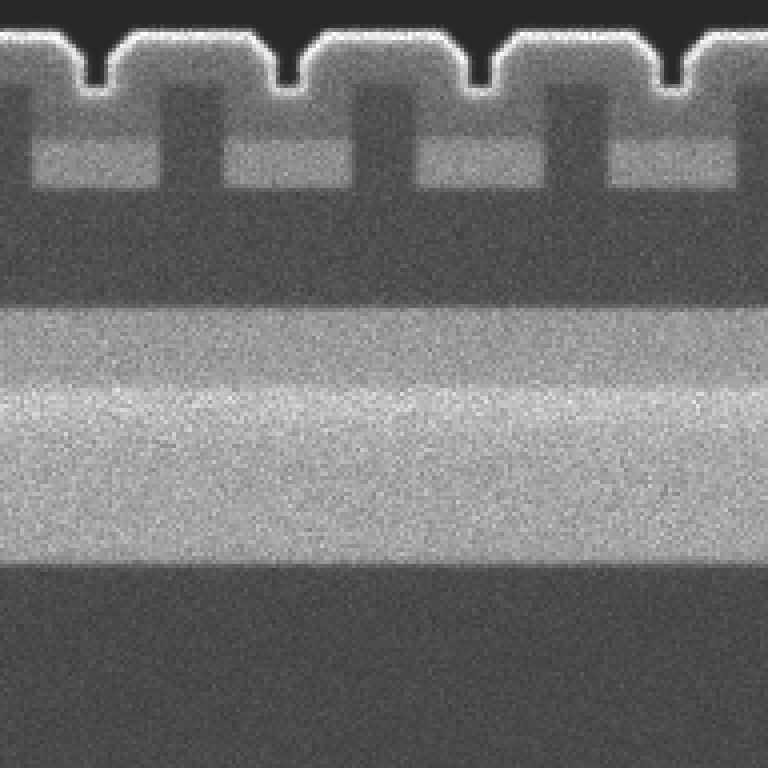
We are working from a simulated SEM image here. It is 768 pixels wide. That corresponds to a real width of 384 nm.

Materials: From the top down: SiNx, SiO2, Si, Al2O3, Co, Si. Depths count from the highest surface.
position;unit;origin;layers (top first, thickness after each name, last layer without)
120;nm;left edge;SiNx 54, SiO2 24, Si 60, Al2O3 40, Co 88, Si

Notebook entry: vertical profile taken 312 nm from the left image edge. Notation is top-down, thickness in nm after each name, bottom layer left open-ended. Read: SiNx 54, SiO2 24, Si 60, Al2O3 40, Co 88, Si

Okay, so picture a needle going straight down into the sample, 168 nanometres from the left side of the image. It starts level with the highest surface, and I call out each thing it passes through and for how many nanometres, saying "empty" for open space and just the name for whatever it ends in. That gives SiNx 54, SiO2 24, Si 60, Al2O3 40, Co 88, Si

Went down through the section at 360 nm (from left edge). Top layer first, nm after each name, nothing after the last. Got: SiNx 54, SiO2 24, Si 60, Al2O3 40, Co 88, Si